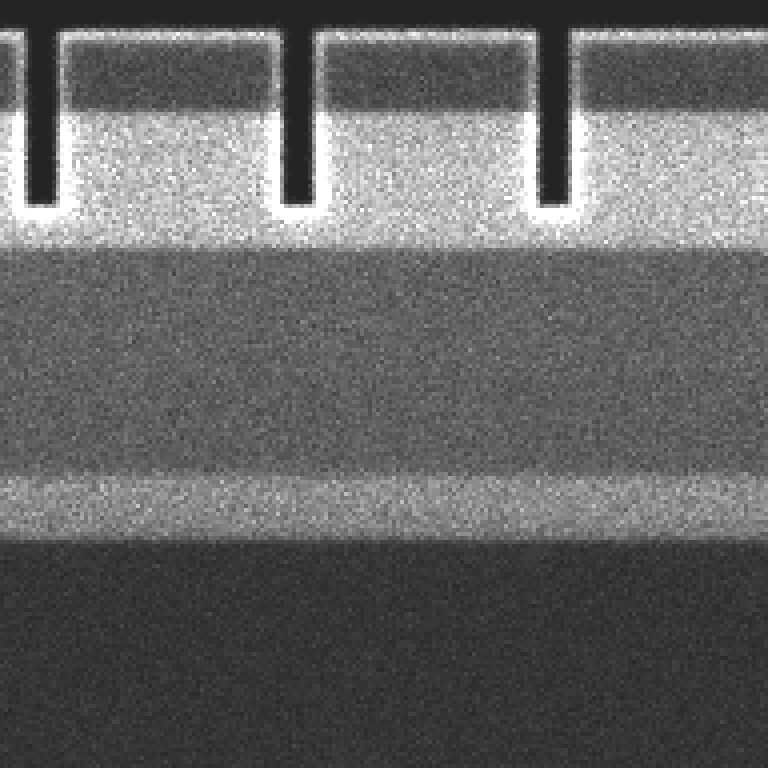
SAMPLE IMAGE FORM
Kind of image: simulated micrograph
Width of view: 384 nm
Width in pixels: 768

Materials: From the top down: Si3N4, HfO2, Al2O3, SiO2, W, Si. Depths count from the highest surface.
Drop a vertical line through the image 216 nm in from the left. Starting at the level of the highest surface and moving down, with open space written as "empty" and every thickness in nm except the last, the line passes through Si3N4 40, HfO2 68, Al2O3 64, SiO2 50, W 32, Si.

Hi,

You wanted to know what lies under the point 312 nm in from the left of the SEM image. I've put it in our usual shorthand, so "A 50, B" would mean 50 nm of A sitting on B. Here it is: Si3N4 40, HfO2 68, Al2O3 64, SiO2 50, W 32, Si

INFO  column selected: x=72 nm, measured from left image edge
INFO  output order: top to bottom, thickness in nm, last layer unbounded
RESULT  Si3N4 40, HfO2 68, Al2O3 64, SiO2 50, W 32, Si